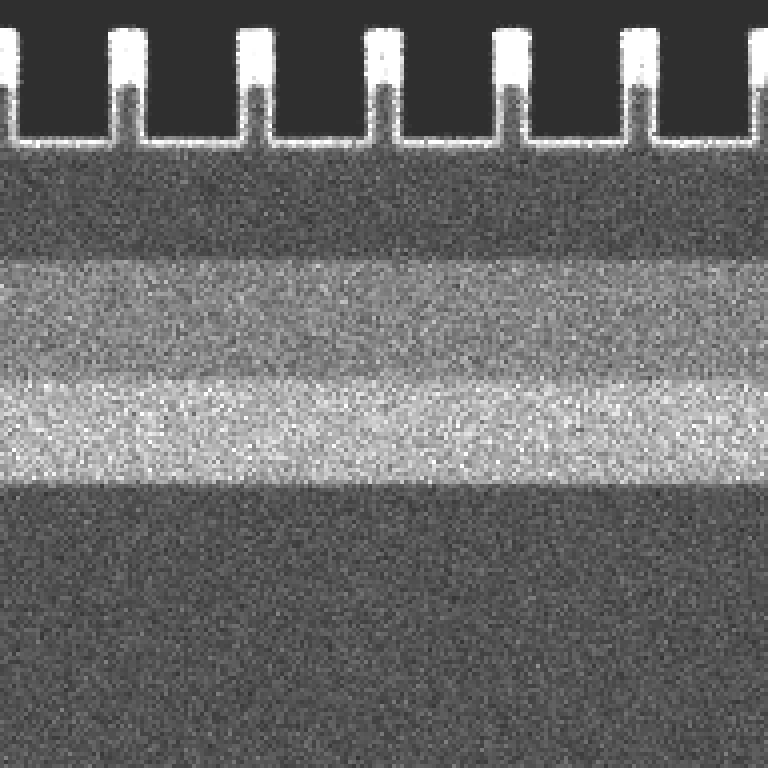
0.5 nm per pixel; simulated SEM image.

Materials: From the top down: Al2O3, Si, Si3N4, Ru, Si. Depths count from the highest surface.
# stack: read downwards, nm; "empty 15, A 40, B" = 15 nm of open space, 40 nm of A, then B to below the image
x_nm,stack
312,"Al2O3 26, Si 88, Si3N4 60, Ru 52, Si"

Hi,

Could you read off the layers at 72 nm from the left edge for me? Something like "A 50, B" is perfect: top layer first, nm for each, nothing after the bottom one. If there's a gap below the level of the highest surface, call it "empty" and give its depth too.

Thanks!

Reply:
empty 54, Si 60, Si3N4 60, Ru 52, Si